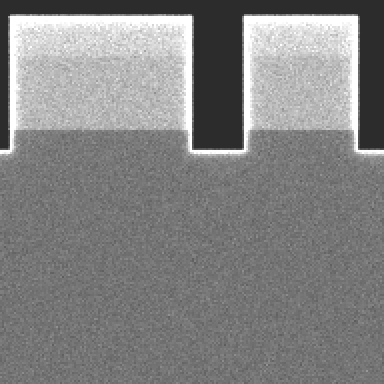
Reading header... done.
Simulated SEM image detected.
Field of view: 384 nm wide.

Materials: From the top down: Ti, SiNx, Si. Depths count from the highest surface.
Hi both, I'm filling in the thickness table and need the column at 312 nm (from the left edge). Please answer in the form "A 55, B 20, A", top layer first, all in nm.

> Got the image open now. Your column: Ti 40, SiNx 74, Si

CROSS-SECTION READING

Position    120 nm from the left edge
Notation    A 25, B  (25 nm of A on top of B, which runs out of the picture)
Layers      Ti 40, SiNx 74, Si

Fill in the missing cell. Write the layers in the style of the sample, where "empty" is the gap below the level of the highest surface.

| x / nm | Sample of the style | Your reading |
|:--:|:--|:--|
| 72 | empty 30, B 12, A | Ti 40, SiNx 74, Si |